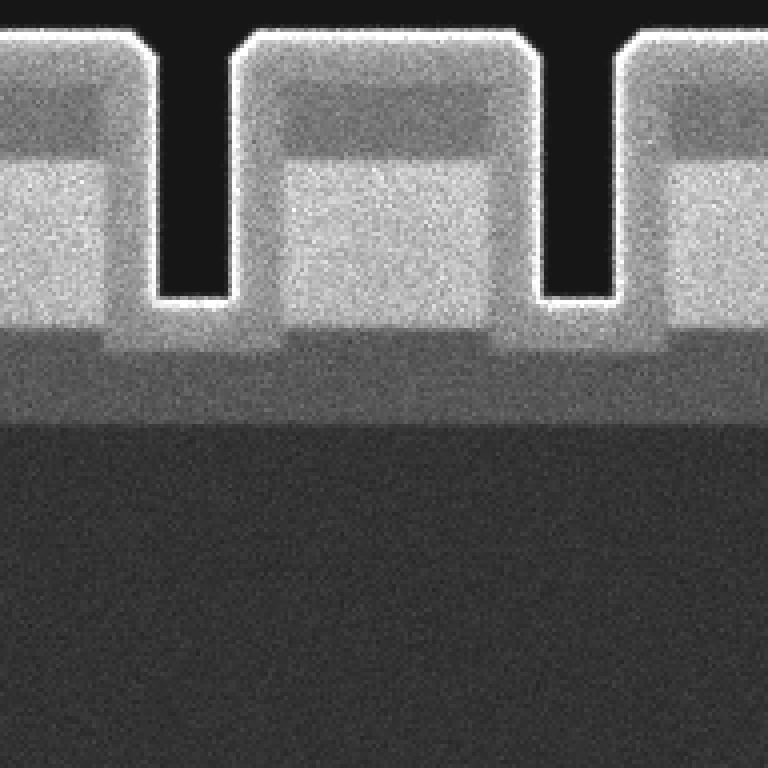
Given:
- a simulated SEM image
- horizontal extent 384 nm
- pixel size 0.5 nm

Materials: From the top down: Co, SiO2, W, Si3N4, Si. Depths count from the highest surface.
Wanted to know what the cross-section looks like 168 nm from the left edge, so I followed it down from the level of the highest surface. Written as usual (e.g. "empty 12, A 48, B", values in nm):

Co 26, SiO2 38, W 84, Si3N4 48, Si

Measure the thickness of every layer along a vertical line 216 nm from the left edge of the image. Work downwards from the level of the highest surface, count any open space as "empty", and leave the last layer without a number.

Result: Co 26, SiO2 38, W 84, Si3N4 48, Si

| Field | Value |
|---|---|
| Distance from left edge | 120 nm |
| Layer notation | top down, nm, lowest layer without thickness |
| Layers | empty 8, Co 152, Si3N4 36, Si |